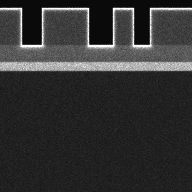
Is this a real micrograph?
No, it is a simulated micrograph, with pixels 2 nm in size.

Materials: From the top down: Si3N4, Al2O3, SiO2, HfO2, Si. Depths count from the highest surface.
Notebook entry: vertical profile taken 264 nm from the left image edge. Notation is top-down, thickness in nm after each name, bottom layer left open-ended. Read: Si3N4 74, Al2O3 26, SiO2 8, HfO2 18, Si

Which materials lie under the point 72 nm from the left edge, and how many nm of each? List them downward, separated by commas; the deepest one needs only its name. empty 74, Al2O3 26, SiO2 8, HfO2 18, Si